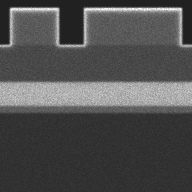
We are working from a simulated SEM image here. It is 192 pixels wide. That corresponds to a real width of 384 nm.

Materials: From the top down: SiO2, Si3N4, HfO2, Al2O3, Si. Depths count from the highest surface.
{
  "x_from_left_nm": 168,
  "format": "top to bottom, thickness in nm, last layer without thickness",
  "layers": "SiO2 74, Si3N4 74, HfO2 48, Al2O3 14, Si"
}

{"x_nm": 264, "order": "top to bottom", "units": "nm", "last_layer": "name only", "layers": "SiO2 74, Si3N4 74, HfO2 48, Al2O3 14, Si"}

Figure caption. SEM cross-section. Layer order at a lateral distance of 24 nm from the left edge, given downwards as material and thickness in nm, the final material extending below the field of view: SiO2 74, Si3N4 74, HfO2 48, Al2O3 14, Si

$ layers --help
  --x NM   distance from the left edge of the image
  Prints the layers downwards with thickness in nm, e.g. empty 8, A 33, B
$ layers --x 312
SiO2 74, Si3N4 74, HfO2 48, Al2O3 14, Si